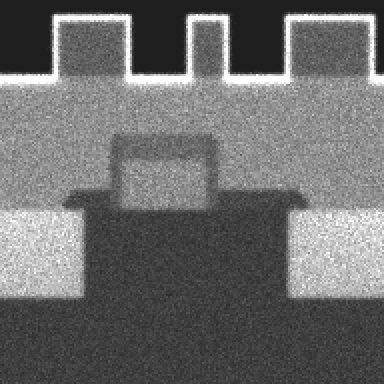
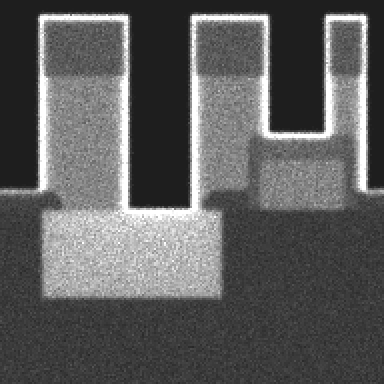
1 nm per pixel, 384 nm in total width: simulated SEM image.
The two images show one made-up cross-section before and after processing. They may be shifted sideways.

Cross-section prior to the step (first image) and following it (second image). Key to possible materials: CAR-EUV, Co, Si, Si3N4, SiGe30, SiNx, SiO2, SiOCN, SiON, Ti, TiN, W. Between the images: SiO2 was removed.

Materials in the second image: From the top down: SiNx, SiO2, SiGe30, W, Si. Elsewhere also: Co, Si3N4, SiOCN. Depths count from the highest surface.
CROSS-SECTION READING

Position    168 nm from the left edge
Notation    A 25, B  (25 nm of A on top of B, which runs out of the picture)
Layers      empty 194, W 88, Si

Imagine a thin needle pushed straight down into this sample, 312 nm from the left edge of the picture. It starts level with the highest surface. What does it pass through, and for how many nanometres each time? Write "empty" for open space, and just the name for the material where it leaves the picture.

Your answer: empty 118, Si3N4 26, Co 50, Si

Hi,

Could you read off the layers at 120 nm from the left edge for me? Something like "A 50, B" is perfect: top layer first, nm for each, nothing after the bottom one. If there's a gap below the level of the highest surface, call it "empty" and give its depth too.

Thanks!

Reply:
SiNx 60, SiO2 134, W 88, Si